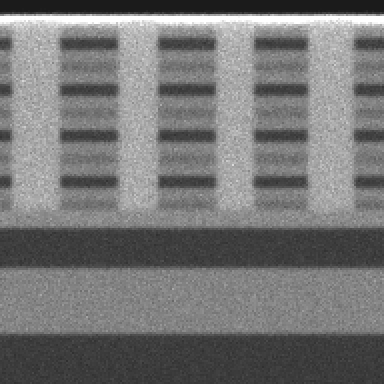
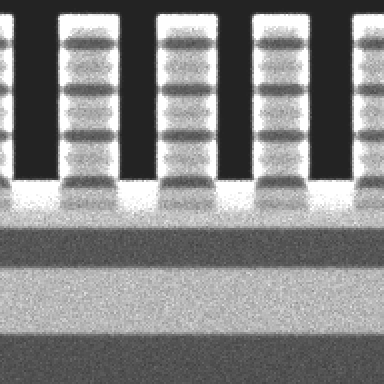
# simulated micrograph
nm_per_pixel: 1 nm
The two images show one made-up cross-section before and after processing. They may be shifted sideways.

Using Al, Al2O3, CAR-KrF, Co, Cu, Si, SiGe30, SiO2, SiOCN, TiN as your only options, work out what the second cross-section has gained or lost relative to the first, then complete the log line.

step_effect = removed Co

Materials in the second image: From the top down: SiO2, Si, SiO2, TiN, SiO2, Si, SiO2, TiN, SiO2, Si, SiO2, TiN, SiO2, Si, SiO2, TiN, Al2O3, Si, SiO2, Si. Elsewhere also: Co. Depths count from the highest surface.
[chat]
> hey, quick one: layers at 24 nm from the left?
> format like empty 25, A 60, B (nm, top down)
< empty 166, Co 28, Al2O3 18, Si 40, SiO2 66, Si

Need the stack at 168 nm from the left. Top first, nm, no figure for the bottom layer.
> SiO2 22, Si 12, SiO2 12, TiN 10, SiO2 12, Si 12, SiO2 12, TiN 10, SiO2 12, Si 12, SiO2 12, TiN 10, SiO2 12, Si 12, SiO2 12, TiN 10, Al2O3 18, Si 40, SiO2 66, Si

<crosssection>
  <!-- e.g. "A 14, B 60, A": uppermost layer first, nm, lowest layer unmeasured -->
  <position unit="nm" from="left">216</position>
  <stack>empty 166, Co 28, Al2O3 18, Si 40, SiO2 66, Si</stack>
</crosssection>